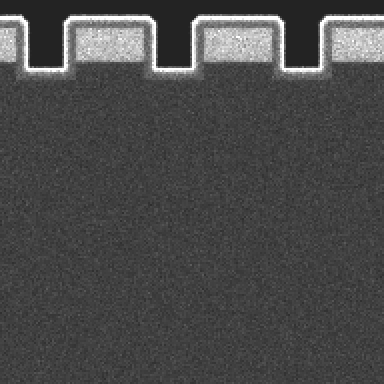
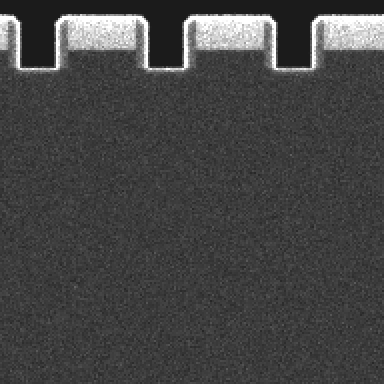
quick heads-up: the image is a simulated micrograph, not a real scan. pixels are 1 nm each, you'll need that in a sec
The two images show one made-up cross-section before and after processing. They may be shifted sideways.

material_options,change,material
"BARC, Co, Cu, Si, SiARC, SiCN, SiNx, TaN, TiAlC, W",removed,SiNx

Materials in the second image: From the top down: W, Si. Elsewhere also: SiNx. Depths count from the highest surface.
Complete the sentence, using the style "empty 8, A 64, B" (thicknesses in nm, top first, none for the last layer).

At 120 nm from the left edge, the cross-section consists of W 34, Si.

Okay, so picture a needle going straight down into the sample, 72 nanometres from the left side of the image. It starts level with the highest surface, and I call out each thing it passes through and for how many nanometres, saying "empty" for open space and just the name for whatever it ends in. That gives W 34, Si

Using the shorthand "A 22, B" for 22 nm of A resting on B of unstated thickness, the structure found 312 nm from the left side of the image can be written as empty 6, SiNx 46, Si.